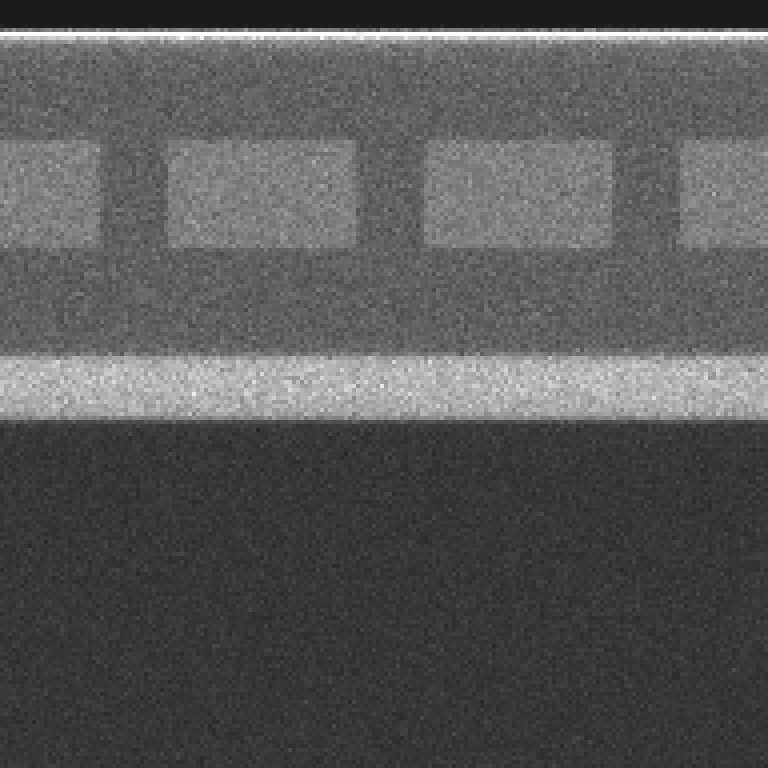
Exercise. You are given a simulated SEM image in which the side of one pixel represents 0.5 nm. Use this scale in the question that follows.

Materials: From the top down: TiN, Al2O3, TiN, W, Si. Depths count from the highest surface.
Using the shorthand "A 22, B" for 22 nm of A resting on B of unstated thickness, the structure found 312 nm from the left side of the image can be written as TiN 162, W 32, Si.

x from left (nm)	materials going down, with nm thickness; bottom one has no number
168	TiN 54, Al2O3 54, TiN 54, W 32, Si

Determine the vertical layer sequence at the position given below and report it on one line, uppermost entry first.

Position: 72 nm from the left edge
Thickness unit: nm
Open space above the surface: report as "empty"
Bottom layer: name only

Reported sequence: TiN 162, W 32, Si